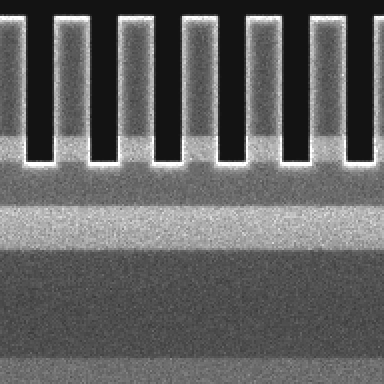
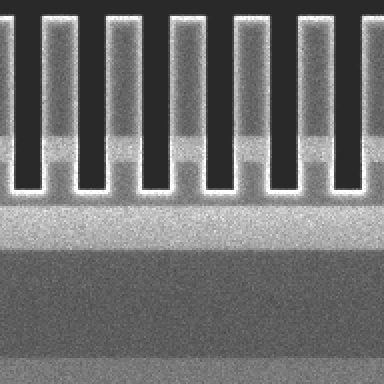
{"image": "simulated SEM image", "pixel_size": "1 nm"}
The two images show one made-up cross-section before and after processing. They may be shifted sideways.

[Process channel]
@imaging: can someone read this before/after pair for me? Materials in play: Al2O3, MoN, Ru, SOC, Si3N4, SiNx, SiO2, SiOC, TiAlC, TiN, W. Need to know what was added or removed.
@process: SiO2 removed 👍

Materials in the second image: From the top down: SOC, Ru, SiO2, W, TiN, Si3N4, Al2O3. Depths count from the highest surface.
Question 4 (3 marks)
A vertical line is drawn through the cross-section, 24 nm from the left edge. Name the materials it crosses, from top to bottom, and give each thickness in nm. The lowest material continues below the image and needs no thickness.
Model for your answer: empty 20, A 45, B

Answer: empty 174, SiO2 16, W 44, TiN 42, Si3N4 66, Al2O3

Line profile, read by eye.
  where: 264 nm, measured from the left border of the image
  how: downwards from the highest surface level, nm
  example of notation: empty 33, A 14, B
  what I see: SOC 120, Ru 26, SiO2 44, W 44, TiN 42, Si3N4 66, Al2O3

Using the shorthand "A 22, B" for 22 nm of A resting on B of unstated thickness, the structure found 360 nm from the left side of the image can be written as empty 174, SiO2 16, W 44, TiN 42, Si3N4 66, Al2O3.